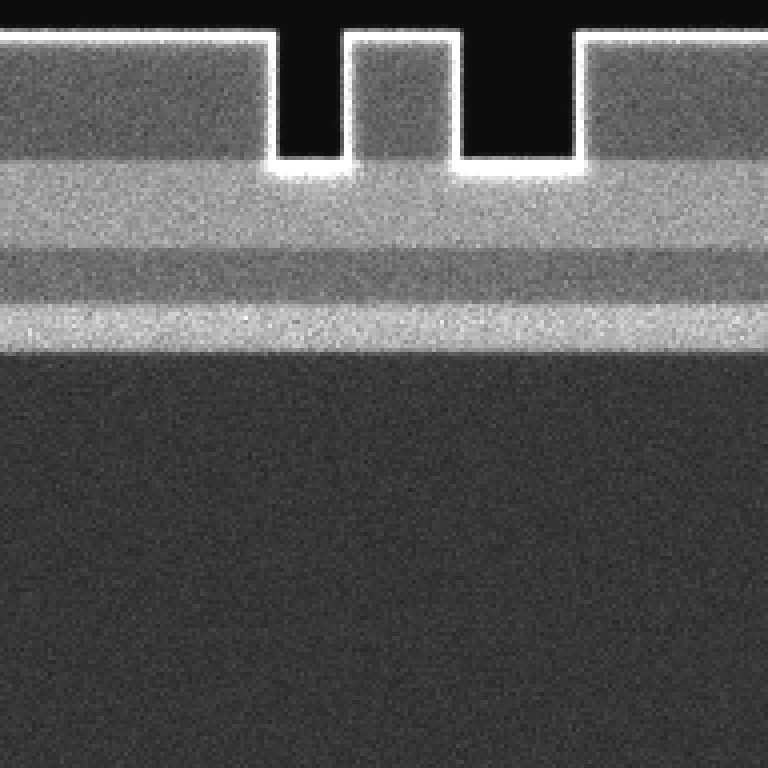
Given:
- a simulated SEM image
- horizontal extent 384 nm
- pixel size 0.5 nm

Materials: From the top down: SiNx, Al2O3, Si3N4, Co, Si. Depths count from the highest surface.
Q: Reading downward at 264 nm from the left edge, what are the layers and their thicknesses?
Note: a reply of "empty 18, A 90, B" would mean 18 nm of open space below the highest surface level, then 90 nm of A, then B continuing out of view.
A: empty 64, Al2O3 44, Si3N4 28, Co 24, Si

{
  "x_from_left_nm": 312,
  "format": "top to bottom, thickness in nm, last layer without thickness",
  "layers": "SiNx 64, Al2O3 44, Si3N4 28, Co 24, Si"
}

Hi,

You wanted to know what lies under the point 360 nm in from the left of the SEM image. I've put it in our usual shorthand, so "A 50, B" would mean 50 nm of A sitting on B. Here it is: SiNx 64, Al2O3 44, Si3N4 28, Co 24, Si